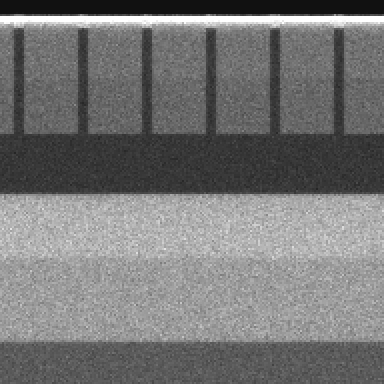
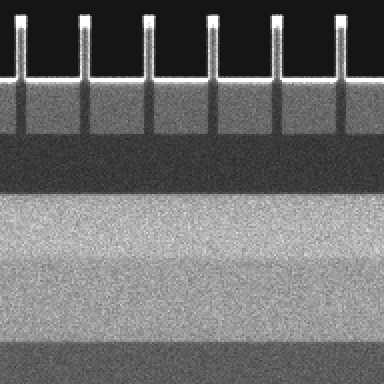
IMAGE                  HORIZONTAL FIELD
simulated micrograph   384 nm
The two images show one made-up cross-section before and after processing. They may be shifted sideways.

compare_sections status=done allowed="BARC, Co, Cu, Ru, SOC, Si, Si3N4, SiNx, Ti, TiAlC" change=removed material="SOC"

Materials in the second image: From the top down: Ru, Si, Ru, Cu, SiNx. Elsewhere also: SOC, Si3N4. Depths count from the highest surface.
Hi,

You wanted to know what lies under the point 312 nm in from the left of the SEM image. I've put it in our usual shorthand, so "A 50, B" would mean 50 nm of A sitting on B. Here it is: empty 62, Si3N4 56, Si 60, Ru 64, Cu 84, SiNx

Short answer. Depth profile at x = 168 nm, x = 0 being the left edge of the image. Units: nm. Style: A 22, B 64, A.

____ empty 62, Si3N4 56, Si 60, Ru 64, Cu 84, SiNx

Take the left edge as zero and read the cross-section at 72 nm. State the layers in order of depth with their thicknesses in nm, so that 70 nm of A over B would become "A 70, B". empty 62, Si3N4 56, Si 60, Ru 64, Cu 84, SiNx